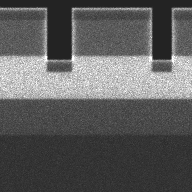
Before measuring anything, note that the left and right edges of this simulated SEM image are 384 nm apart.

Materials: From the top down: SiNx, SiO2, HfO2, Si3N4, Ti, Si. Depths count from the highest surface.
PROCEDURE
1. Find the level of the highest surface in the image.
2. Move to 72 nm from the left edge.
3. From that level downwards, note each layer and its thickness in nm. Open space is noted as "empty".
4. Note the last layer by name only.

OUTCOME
SiNx 24, SiO2 72, HfO2 86, Si3N4 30, Ti 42, Si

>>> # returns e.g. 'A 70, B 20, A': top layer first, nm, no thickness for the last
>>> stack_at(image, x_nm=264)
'SiNx 24, SiO2 72, HfO2 86, Si3N4 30, Ti 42, Si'